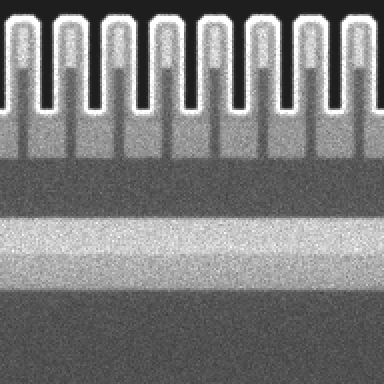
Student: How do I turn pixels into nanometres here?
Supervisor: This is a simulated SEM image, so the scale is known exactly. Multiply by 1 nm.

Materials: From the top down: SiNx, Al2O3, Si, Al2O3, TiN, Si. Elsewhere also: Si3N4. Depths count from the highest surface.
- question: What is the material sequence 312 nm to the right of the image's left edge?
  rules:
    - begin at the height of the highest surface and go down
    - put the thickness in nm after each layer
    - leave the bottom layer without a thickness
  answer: SiNx 12, Al2O3 40, Si 150, Al2O3 36, TiN 36, Si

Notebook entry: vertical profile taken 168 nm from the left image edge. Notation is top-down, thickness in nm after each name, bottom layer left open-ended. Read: SiNx 12, Al2O3 40, Si 150, Al2O3 36, TiN 36, Si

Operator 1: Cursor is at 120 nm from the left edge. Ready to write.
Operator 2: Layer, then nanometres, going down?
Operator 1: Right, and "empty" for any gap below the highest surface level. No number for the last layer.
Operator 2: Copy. SiNx 12, Al2O3 40, Si 150, Al2O3 36, TiN 36, Si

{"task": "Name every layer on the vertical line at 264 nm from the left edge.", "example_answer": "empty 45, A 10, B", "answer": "SiNx 12, Al2O3 40, Si 150, Al2O3 36, TiN 36, Si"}